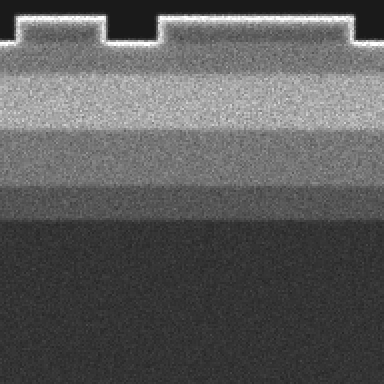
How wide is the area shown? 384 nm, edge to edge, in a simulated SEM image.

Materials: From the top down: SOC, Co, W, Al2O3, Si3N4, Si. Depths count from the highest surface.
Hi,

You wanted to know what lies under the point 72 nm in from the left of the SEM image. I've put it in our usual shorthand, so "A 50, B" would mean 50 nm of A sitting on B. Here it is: SOC 26, Co 32, W 56, Al2O3 56, Si3N4 34, Si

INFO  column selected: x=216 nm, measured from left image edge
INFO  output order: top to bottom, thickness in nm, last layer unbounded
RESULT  SOC 26, Co 32, W 56, Al2O3 56, Si3N4 34, Si